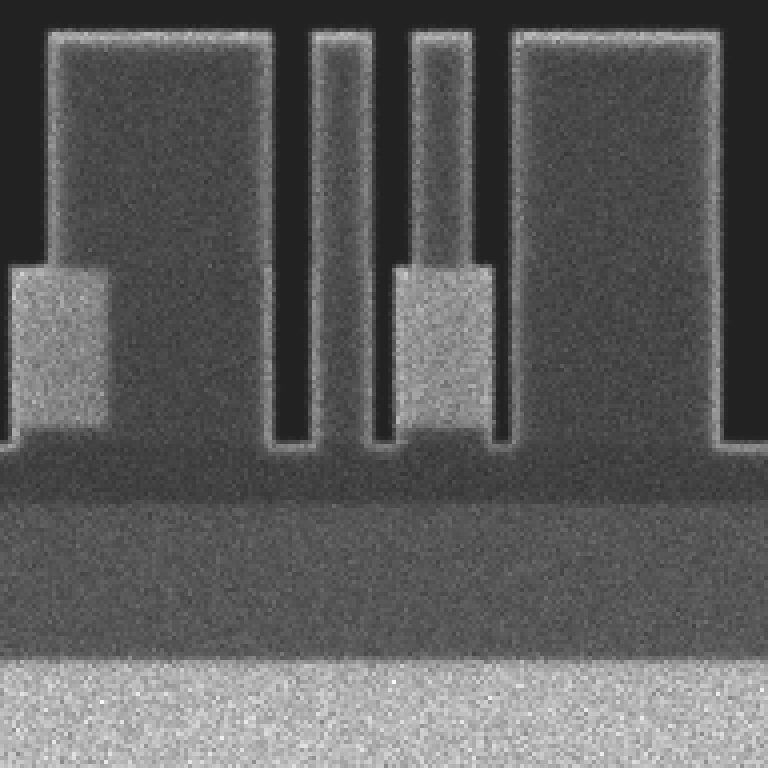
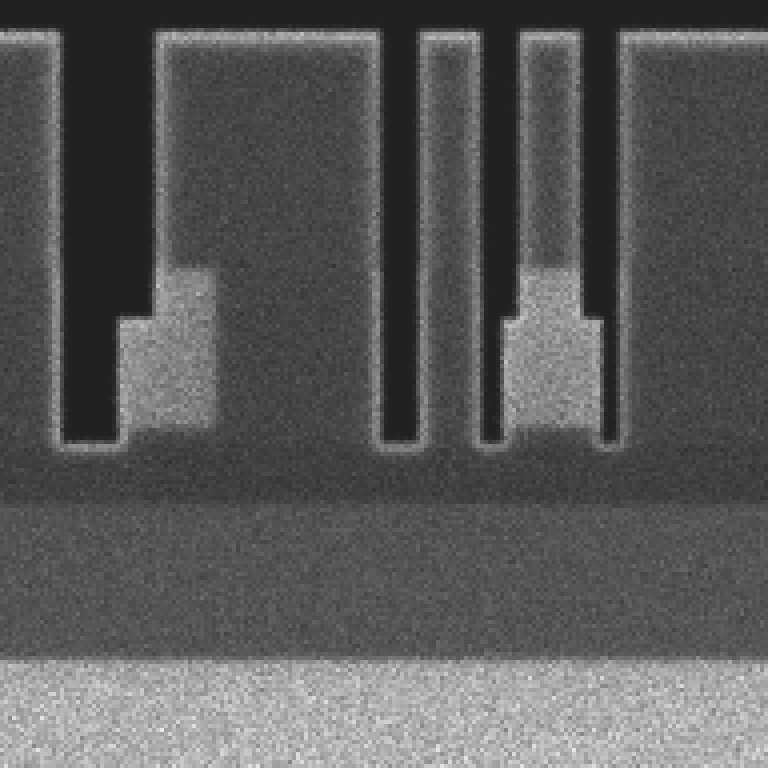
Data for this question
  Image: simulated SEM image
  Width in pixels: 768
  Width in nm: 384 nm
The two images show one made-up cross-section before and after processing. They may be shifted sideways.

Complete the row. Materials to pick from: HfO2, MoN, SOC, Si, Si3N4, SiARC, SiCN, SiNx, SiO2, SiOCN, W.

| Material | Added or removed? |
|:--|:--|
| W | removed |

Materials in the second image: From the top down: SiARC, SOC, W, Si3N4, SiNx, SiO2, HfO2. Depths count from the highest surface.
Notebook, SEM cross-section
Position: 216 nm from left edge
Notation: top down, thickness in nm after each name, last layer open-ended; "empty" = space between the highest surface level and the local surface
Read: SiARC 20, SOC 98, Si3N4 88, SiNx 30, SiO2 78, HfO2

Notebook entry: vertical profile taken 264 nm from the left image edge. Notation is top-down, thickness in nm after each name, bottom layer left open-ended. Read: SiARC 20, SOC 98, W 80, Si3N4 8, SiNx 30, SiO2 78, HfO2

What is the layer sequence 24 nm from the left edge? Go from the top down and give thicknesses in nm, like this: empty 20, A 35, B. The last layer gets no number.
SiARC 20, SOC 98, Si3N4 88, SiNx 30, SiO2 78, HfO2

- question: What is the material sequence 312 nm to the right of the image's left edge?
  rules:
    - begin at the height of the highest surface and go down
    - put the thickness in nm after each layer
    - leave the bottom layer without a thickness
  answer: SiARC 20, SOC 98, Si3N4 88, SiNx 30, SiO2 78, HfO2